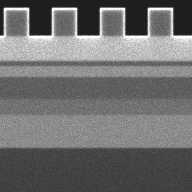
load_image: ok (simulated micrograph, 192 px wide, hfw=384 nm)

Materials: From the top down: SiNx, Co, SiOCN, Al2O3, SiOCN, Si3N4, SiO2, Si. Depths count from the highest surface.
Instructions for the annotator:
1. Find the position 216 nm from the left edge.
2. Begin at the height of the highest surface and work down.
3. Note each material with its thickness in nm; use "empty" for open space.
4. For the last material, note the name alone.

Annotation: SiNx 56, Co 50, SiOCN 10, Al2O3 22, SiOCN 44, Si3N4 32, SiO2 66, Si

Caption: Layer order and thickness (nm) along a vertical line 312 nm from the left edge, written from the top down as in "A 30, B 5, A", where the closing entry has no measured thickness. SiNx 56, Co 50, SiOCN 10, Al2O3 22, SiOCN 44, Si3N4 32, SiO2 66, Si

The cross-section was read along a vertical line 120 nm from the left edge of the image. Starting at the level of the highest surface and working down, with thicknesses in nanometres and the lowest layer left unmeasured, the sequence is SiNx 56, Co 50, SiOCN 10, Al2O3 22, SiOCN 44, Si3N4 32, SiO2 66, Si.